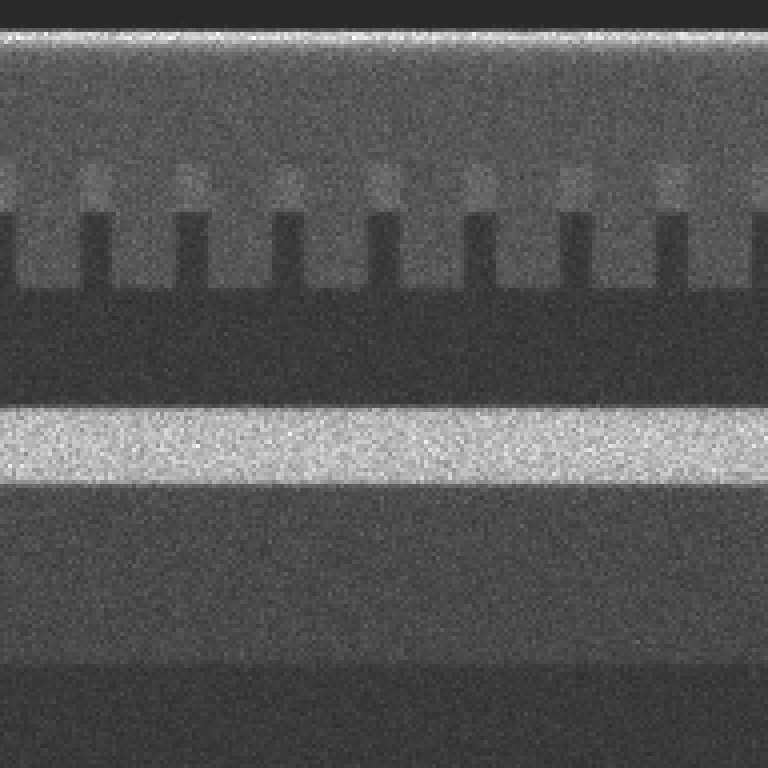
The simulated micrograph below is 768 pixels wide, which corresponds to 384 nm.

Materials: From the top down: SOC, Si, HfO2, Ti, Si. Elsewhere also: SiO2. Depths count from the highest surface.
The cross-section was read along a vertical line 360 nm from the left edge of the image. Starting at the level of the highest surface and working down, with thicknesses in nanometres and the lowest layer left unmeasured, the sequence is SOC 128, Si 60, HfO2 38, Ti 90, Si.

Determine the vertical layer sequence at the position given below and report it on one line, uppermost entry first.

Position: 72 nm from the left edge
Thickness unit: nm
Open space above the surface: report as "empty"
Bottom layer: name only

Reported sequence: SOC 128, Si 60, HfO2 38, Ti 90, Si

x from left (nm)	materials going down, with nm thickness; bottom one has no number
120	SOC 128, Si 60, HfO2 38, Ti 90, Si